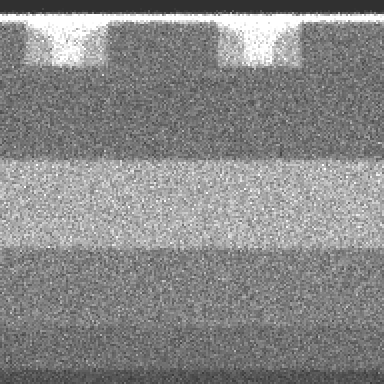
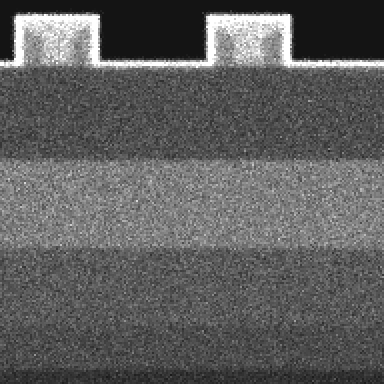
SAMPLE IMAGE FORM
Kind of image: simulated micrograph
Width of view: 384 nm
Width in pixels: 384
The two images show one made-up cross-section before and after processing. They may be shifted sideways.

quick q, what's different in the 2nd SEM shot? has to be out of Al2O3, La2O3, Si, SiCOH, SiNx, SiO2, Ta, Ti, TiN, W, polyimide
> SiNx removed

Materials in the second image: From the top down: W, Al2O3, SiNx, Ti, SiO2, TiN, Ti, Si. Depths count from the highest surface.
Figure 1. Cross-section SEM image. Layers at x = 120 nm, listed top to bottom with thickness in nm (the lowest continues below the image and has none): empty 46, SiNx 18, Ti 80, SiO2 88, TiN 78, Ti 44, Si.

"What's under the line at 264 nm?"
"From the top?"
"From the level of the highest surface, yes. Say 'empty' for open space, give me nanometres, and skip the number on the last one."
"W 24, Al2O3 26, SiNx 14, Ti 80, SiO2 88, TiN 78, Ti 44, Si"